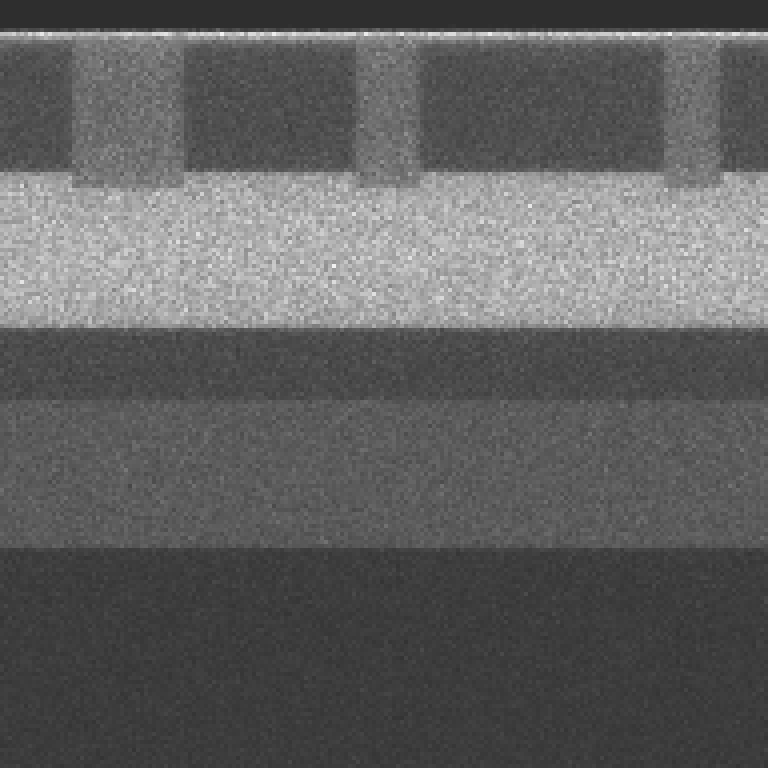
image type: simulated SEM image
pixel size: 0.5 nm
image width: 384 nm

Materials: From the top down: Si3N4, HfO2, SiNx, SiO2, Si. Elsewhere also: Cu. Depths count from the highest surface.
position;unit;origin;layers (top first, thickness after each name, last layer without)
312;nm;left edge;Si3N4 70, HfO2 78, SiNx 36, SiO2 74, Si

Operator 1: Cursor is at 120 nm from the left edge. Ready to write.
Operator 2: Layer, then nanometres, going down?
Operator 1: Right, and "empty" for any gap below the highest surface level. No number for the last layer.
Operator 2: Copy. Si3N4 70, HfO2 78, SiNx 36, SiO2 74, Si